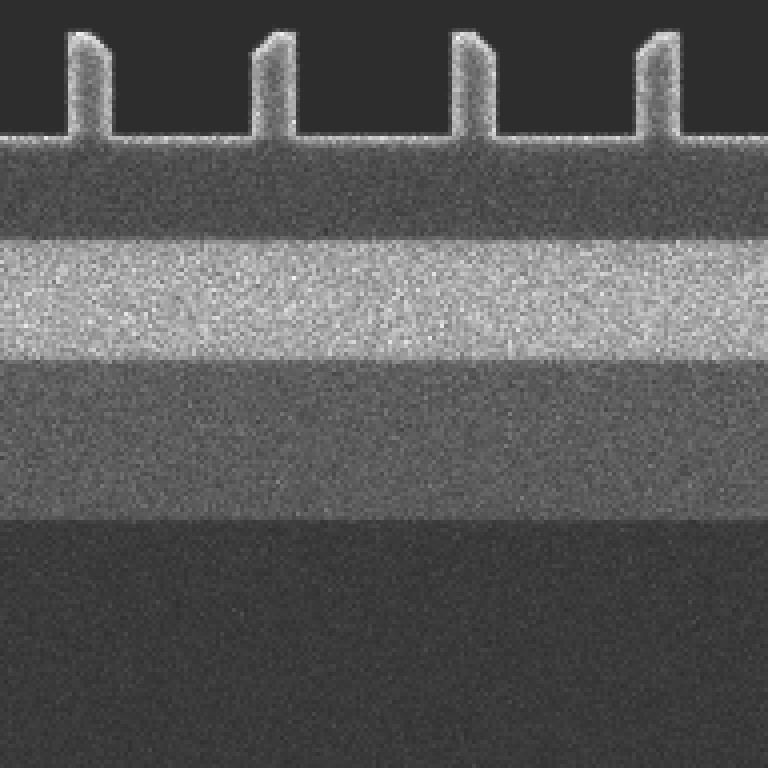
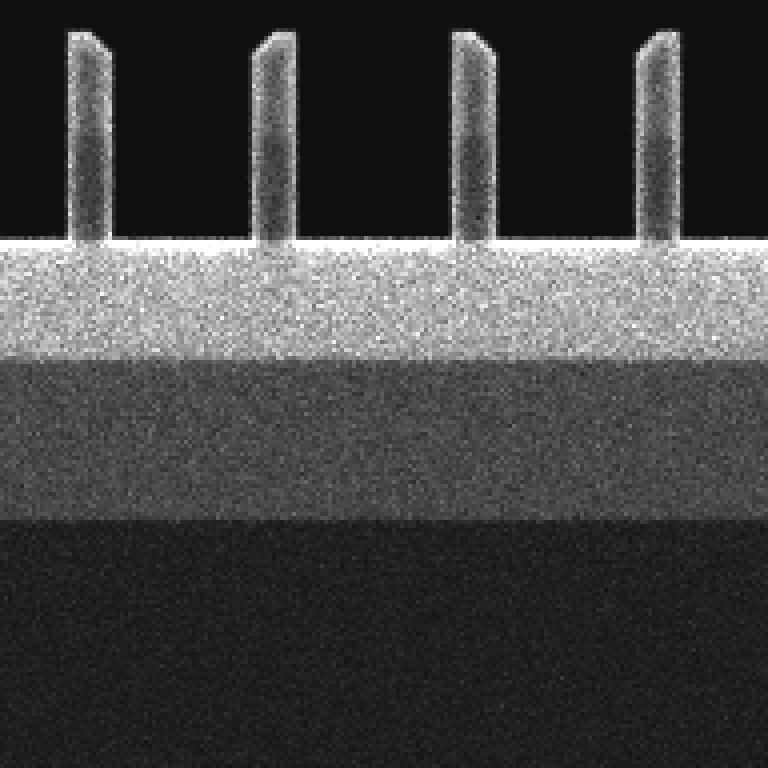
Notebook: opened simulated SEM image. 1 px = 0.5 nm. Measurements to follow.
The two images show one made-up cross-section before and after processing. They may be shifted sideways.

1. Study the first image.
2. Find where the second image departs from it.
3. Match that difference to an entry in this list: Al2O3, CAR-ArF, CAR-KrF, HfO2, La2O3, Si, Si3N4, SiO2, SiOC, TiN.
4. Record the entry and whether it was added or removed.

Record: Si3N4 / removed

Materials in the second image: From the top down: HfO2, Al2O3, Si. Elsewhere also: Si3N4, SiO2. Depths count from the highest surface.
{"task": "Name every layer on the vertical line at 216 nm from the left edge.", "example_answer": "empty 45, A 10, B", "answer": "empty 104, HfO2 60, Al2O3 80, Si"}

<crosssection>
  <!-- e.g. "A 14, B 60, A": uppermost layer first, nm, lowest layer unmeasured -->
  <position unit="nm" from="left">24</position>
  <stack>empty 104, HfO2 60, Al2O3 80, Si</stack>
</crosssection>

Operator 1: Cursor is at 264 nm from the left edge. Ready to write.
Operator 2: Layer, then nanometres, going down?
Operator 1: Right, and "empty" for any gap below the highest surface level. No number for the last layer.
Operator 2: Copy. empty 104, HfO2 60, Al2O3 80, Si